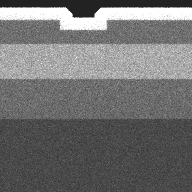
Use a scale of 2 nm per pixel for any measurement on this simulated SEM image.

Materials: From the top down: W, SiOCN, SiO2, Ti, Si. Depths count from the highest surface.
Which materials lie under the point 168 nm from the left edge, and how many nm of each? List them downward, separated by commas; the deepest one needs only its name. empty 20, W 24, SiOCN 28, SiO2 70, Ti 80, Si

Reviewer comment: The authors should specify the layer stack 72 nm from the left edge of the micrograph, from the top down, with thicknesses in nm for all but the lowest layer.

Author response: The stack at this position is W 24, SiOCN 48, SiO2 70, Ti 80, Si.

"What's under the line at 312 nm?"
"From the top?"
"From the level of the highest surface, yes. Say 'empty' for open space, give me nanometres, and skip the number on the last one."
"W 24, SiOCN 48, SiO2 70, Ti 80, Si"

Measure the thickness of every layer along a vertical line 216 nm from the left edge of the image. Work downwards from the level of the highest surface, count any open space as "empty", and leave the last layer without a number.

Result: W 24, SiOCN 48, SiO2 70, Ti 80, Si